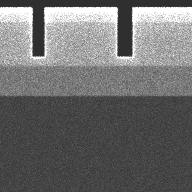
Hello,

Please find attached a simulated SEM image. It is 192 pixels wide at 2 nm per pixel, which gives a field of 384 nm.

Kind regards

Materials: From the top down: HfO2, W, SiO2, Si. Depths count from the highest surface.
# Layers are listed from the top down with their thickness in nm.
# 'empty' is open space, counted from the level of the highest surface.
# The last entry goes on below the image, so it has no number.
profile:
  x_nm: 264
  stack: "empty 98, W 18, SiO2 60, Si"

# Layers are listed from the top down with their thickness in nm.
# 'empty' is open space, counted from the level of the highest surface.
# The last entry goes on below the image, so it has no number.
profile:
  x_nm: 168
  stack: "HfO2 28, W 88, SiO2 60, Si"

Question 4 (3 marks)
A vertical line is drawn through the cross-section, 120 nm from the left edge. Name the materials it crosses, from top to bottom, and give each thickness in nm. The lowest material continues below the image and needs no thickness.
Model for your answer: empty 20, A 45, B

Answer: HfO2 28, W 88, SiO2 60, Si